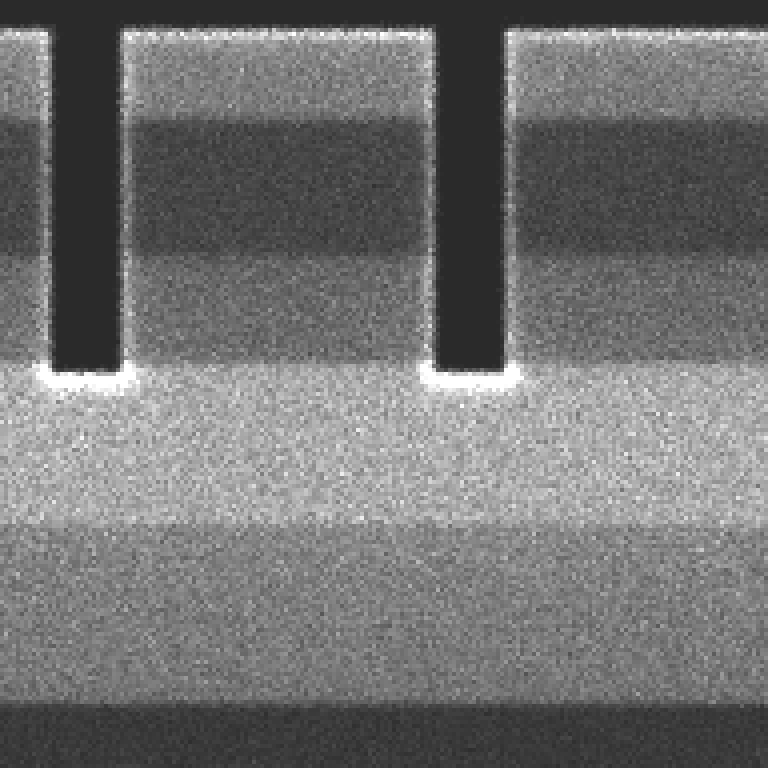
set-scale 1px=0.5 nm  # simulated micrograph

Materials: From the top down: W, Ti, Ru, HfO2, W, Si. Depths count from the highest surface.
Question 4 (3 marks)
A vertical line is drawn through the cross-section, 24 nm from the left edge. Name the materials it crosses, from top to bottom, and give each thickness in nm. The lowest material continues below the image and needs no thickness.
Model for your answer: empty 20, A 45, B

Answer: empty 172, HfO2 74, W 90, Si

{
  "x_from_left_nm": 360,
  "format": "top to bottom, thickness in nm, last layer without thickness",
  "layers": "W 44, Ti 68, Ru 54, HfO2 80, W 90, Si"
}